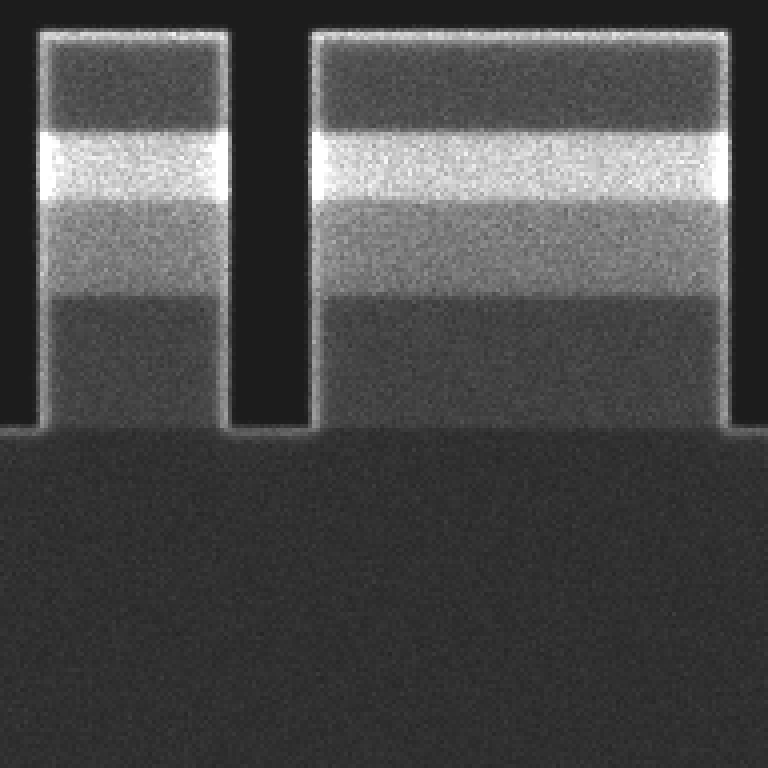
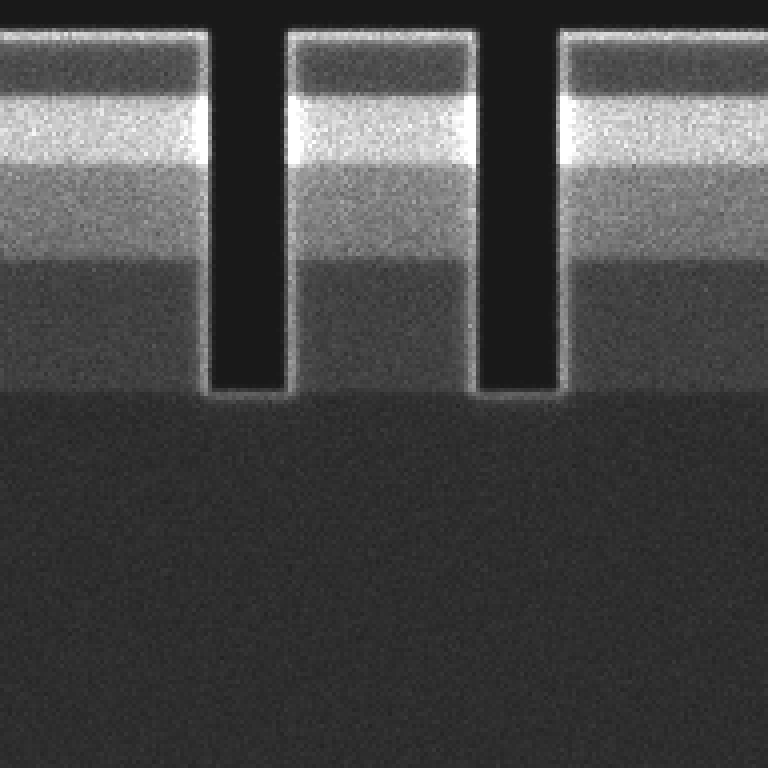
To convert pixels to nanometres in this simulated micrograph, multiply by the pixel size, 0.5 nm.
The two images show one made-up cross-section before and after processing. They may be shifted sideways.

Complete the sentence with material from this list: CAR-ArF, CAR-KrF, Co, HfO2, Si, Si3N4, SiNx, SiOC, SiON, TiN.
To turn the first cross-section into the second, Si3N4 must be removed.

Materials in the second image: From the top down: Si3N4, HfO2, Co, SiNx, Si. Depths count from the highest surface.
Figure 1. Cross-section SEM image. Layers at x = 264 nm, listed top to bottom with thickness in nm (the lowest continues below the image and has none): empty 180, Si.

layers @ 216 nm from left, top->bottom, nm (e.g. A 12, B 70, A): Si3N4 32, HfO2 34, Co 48, SiNx 66, Si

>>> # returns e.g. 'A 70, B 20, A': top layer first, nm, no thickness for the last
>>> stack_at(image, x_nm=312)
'Si3N4 32, HfO2 34, Co 48, SiNx 66, Si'